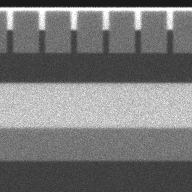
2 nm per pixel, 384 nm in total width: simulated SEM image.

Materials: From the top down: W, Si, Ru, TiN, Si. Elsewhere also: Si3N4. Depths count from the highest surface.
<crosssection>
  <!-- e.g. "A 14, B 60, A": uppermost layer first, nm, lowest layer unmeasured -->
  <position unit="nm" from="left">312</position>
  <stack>Si3N4 90, Si 60, Ru 90, TiN 66, Si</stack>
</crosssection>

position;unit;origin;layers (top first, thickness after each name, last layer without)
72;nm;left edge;Si3N4 90, Si 60, Ru 90, TiN 66, Si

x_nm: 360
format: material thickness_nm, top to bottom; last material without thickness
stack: Si3N4 90, Si 60, Ru 90, TiN 66, Si